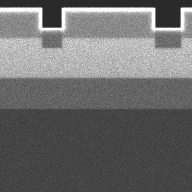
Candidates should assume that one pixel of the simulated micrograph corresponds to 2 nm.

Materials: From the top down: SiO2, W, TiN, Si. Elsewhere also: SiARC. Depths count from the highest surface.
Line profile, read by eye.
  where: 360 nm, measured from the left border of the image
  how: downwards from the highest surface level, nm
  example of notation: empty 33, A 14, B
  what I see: empty 40, SiARC 40, W 60, TiN 62, Si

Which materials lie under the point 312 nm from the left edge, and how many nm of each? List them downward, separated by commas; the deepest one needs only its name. empty 40, SiARC 40, W 60, TiN 62, Si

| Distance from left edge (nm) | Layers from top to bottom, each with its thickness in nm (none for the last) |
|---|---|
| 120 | empty 40, SiARC 40, W 60, TiN 62, Si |